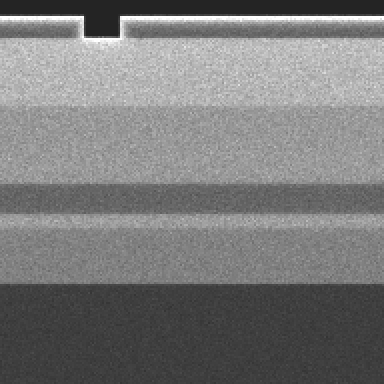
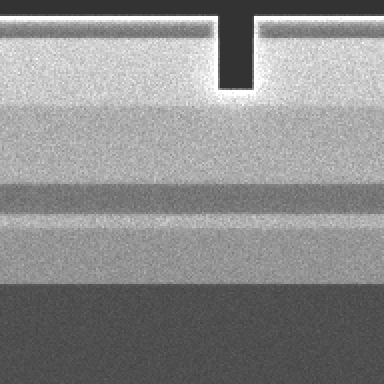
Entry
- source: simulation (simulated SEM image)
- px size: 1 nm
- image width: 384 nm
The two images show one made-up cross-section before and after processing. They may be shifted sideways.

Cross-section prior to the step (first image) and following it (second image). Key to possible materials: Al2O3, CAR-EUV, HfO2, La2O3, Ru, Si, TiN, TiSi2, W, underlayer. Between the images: W was removed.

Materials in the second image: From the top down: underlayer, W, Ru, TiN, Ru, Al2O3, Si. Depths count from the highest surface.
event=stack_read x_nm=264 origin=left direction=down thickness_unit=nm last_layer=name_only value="underlayer 22, W 68, Ru 78, TiN 30, Ru 14, Al2O3 56, Si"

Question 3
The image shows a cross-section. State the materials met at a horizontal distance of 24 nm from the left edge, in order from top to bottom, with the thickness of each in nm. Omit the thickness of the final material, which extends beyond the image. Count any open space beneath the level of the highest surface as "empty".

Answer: underlayer 22, W 68, Ru 78, TiN 30, Ru 14, Al2O3 56, Si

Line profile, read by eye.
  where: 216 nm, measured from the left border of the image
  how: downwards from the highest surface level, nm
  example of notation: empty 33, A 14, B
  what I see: underlayer 22, W 68, Ru 78, TiN 30, Ru 14, Al2O3 56, Si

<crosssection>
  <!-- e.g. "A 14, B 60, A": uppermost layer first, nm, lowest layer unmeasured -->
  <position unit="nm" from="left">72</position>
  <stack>underlayer 22, W 68, Ru 78, TiN 30, Ru 14, Al2O3 56, Si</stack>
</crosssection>